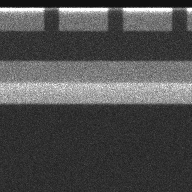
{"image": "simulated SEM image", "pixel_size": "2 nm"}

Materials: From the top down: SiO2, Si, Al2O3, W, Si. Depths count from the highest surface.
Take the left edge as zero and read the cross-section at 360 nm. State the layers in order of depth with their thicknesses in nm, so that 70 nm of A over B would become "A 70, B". Si 106, Al2O3 44, W 42, Si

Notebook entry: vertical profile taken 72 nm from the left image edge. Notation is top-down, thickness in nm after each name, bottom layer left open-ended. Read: SiO2 46, Si 60, Al2O3 44, W 42, Si